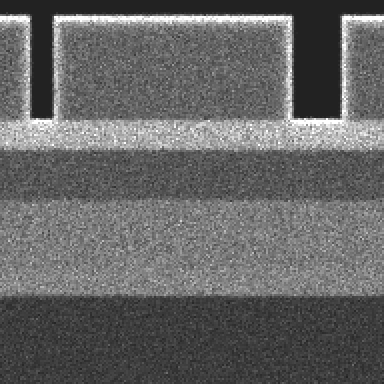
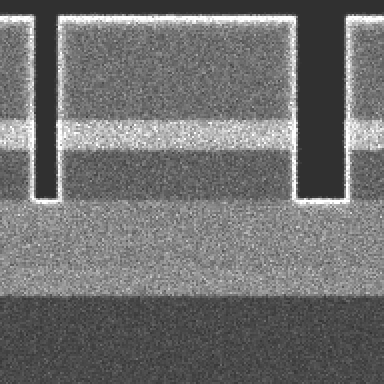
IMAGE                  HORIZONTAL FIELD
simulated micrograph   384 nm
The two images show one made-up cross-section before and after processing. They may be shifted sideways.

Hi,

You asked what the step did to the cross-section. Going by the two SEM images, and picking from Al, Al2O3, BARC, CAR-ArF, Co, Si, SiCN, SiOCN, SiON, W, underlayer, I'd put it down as SiOCN and W, removed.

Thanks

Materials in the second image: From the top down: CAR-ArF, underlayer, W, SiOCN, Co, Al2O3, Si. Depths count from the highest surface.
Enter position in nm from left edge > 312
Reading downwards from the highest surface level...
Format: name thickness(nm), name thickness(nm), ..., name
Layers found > empty 184, Co 68, Al2O3 28, Si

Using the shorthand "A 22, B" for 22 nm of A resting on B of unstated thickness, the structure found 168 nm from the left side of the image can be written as CAR-ArF 80, underlayer 24, W 30, SiOCN 50, Co 68, Al2O3 28, Si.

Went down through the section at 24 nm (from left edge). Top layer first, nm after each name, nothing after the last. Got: CAR-ArF 80, underlayer 24, W 30, SiOCN 50, Co 68, Al2O3 28, Si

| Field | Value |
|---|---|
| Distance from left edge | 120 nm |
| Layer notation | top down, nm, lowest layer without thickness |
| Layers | CAR-ArF 80, underlayer 24, W 30, SiOCN 50, Co 68, Al2O3 28, Si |